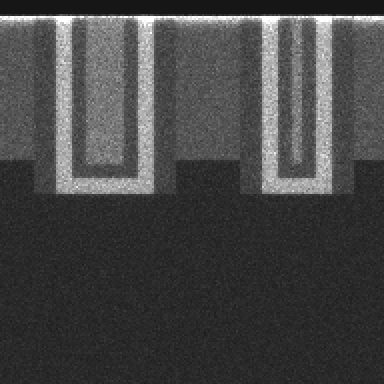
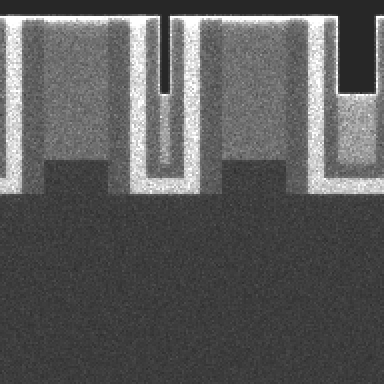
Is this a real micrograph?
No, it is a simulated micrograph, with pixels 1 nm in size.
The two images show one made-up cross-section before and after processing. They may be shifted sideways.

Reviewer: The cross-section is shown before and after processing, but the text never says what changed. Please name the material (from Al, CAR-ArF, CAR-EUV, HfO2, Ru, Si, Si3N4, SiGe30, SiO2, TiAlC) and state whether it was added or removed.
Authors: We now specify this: Ru, removed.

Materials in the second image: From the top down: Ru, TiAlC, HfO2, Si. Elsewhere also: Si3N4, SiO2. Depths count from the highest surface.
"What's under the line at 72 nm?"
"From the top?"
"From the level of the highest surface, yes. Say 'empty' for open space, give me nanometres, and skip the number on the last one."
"SiO2 144, Si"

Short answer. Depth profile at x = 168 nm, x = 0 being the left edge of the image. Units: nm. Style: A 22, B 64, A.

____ empty 78, Ru 70, TiAlC 14, HfO2 16, Si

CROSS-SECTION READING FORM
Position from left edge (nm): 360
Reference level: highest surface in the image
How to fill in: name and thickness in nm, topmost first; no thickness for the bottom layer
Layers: empty 78, Ru 70, TiAlC 14, HfO2 16, Si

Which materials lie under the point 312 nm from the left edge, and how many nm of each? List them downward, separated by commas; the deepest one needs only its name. HfO2 178, Si